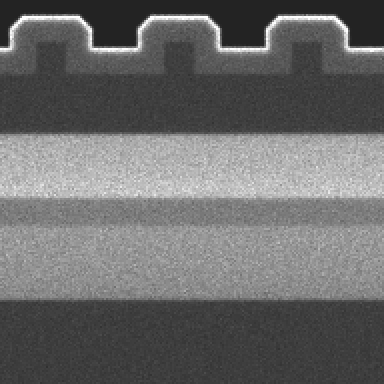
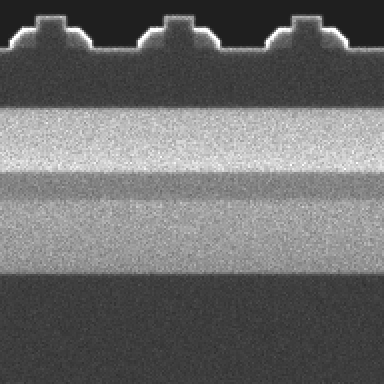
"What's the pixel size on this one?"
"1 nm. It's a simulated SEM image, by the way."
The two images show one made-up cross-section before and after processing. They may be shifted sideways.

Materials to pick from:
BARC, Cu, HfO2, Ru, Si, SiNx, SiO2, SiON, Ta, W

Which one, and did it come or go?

SiNx - removed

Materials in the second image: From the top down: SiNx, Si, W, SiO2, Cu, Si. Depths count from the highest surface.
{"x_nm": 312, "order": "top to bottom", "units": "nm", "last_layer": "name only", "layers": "Si 92, W 64, SiO2 28, Cu 74, Si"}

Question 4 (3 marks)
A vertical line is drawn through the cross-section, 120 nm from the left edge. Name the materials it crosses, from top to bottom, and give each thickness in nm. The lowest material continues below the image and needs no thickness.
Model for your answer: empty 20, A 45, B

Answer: empty 32, Si 60, W 64, SiO2 28, Cu 74, Si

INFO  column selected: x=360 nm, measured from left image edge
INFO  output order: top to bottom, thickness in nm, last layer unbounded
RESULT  empty 32, Si 60, W 64, SiO2 28, Cu 74, Si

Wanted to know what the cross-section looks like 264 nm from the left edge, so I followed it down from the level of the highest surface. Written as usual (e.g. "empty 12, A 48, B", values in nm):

empty 32, Si 60, W 64, SiO2 28, Cu 74, Si